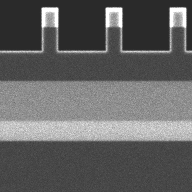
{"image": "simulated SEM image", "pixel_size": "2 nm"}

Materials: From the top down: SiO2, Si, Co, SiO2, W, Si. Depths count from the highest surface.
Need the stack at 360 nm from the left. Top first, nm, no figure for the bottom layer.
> SiO2 38, Si 108, Co 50, SiO2 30, W 40, Si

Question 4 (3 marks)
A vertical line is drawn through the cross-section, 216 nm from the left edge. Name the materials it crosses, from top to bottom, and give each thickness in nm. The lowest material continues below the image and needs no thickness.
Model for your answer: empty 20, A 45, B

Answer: SiO2 38, Si 108, Co 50, SiO2 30, W 40, Si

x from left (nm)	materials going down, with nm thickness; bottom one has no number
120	empty 86, Si 60, Co 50, SiO2 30, W 40, Si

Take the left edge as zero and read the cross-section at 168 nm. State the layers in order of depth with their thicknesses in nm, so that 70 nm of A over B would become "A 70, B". empty 86, Si 60, Co 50, SiO2 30, W 40, Si